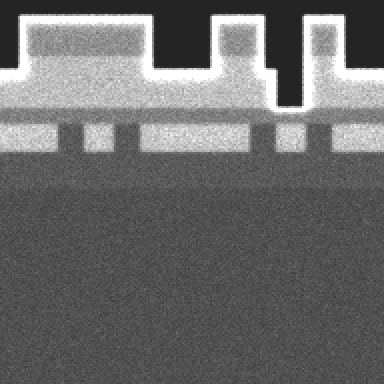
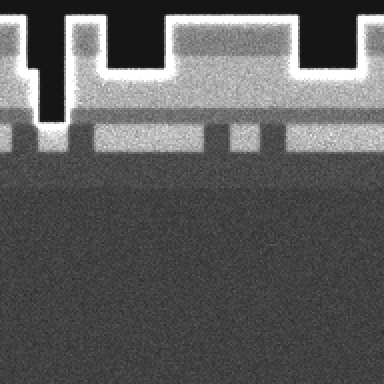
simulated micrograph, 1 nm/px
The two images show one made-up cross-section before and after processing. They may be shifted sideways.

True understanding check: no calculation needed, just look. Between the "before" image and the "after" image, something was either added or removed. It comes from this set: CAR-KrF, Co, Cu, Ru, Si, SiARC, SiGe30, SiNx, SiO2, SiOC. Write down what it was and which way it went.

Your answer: SiNx (removed)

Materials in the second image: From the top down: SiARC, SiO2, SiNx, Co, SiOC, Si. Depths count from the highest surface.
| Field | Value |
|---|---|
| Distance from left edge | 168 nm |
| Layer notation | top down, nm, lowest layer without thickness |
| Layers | SiARC 40, SiO2 52, SiNx 16, Co 28, SiOC 36, Si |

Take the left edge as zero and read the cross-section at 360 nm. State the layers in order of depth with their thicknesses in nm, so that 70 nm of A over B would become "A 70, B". SiARC 40, SiO2 52, SiNx 16, Co 28, SiOC 36, Si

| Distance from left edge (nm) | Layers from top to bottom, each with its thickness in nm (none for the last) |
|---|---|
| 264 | SiARC 40, SiO2 52, SiNx 16, SiOC 64, Si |